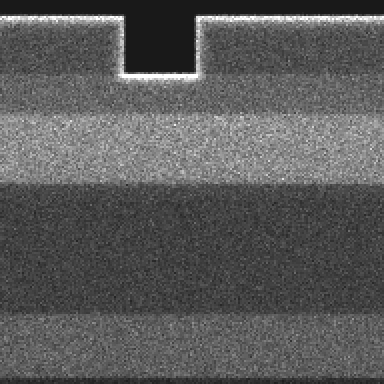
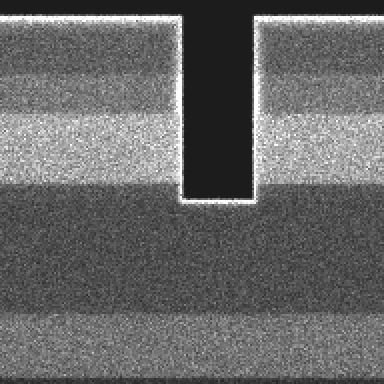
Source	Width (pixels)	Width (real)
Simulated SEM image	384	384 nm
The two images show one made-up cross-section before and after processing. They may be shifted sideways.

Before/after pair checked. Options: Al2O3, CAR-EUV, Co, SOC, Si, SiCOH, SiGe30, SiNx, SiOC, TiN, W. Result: removed Al2O3 and TiN and W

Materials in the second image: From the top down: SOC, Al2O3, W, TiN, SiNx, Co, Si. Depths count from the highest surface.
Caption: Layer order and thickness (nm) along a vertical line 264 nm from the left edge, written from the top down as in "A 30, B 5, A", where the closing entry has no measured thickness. SOC 58, Al2O3 40, W 70, TiN 16, SiNx 114, Co 64, Si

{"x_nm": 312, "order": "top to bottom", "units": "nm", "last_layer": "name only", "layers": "SOC 58, Al2O3 40, W 70, TiN 16, SiNx 114, Co 64, Si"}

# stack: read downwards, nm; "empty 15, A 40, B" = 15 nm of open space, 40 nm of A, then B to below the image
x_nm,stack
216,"empty 184, SiNx 114, Co 64, Si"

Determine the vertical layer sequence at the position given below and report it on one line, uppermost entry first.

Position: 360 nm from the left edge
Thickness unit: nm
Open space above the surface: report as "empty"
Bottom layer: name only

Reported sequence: SOC 58, Al2O3 40, W 70, TiN 16, SiNx 114, Co 64, Si